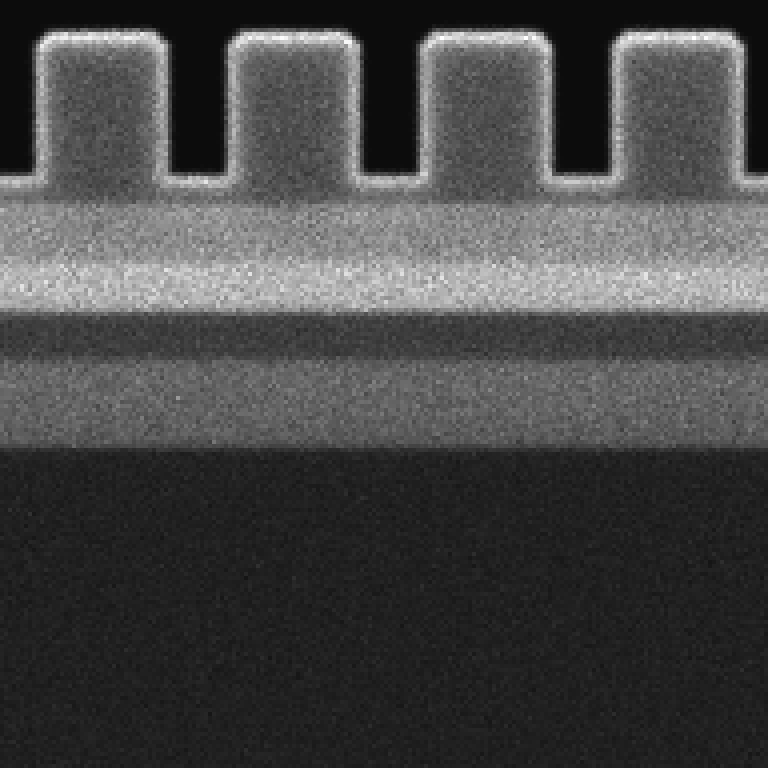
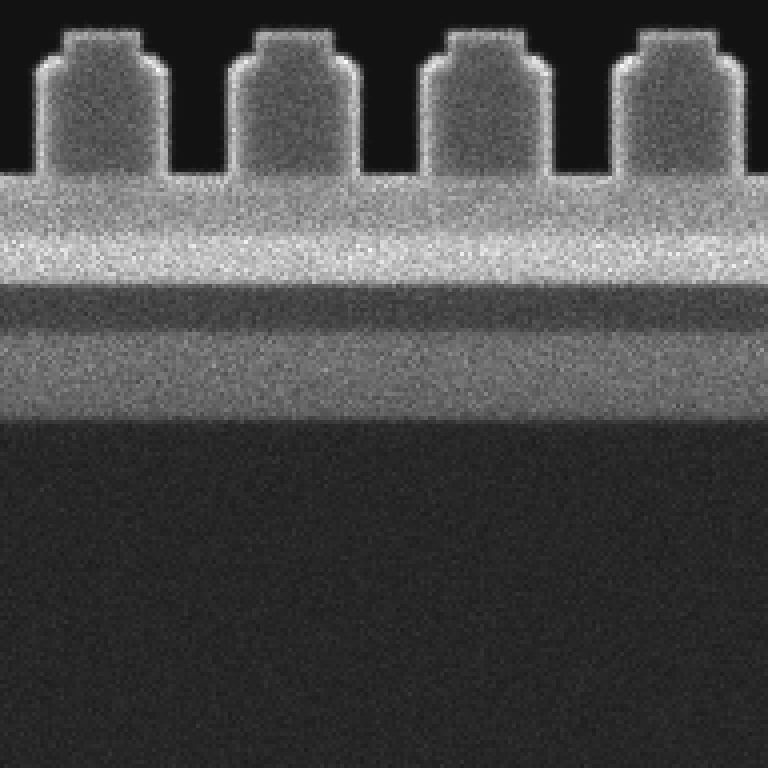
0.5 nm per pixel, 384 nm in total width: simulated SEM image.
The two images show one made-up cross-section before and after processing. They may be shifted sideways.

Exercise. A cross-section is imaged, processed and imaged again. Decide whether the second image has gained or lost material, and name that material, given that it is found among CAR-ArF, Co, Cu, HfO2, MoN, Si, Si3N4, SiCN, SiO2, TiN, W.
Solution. removed: SiO2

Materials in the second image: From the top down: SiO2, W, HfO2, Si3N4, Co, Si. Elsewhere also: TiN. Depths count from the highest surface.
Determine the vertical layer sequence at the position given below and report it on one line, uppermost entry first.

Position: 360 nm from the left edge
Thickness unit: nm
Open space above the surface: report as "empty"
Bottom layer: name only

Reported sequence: empty 12, SiO2 60, W 30, HfO2 24, Si3N4 24, Co 44, Si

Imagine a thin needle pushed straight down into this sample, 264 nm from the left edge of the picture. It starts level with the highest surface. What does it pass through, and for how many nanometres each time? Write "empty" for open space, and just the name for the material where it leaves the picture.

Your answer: empty 12, SiO2 60, W 30, HfO2 24, Si3N4 24, Co 44, Si